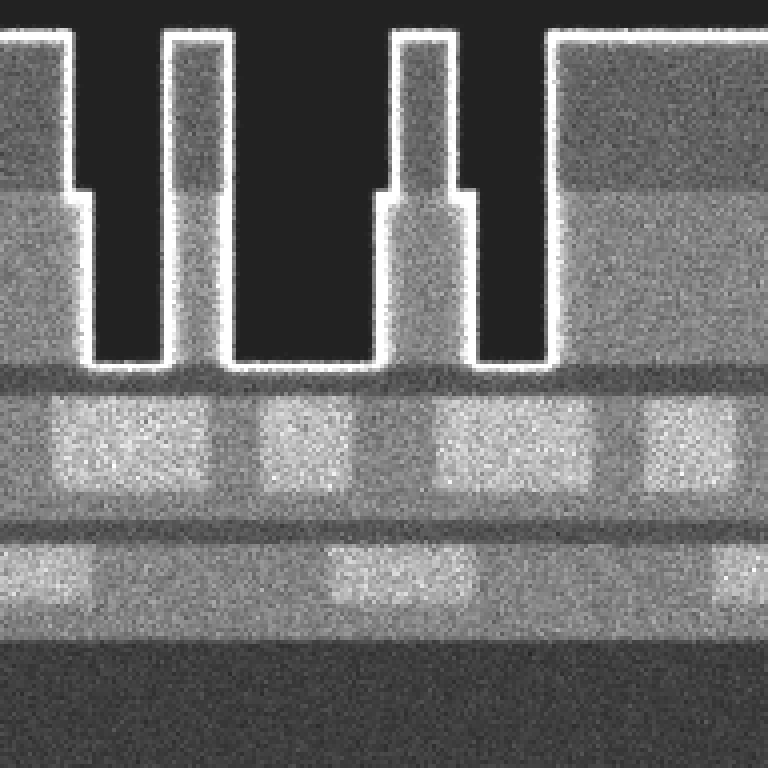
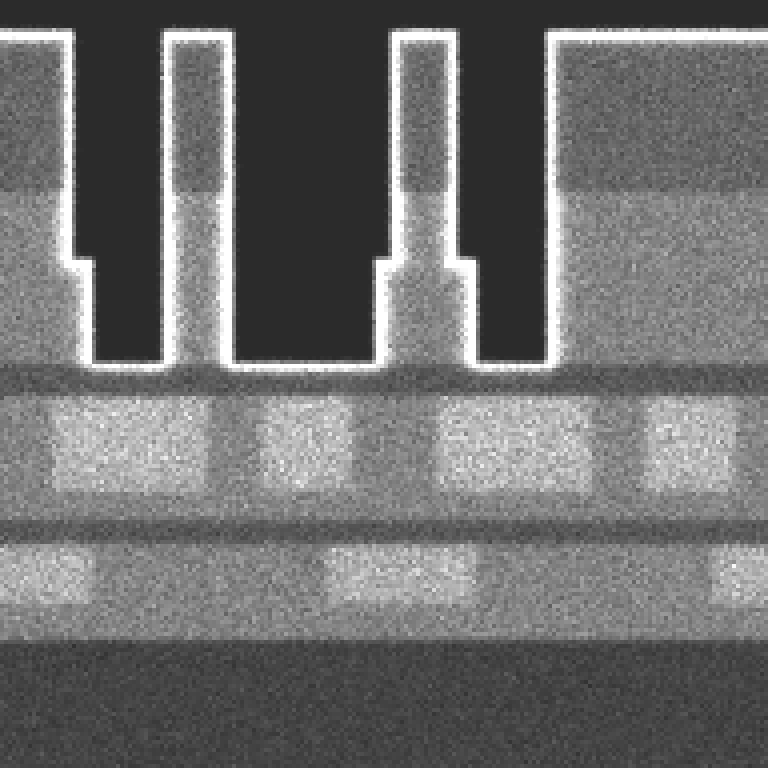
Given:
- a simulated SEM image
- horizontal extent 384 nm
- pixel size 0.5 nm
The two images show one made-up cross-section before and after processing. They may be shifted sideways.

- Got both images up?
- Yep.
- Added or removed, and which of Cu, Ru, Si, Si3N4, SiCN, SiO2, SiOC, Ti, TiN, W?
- removed, SiO2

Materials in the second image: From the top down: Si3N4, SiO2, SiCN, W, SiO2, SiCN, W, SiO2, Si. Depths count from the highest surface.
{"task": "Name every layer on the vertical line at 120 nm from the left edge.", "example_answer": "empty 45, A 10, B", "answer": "empty 166, SiCN 16, SiO2 62, SiCN 12, SiO2 48, Si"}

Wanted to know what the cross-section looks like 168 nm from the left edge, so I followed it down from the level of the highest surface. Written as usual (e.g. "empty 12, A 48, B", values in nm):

empty 166, SiCN 16, W 48, SiO2 14, SiCN 12, W 30, SiO2 18, Si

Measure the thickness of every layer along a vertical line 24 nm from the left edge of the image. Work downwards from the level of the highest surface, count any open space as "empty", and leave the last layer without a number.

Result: Si3N4 80, SiO2 86, SiCN 16, SiO2 62, SiCN 12, W 30, SiO2 18, Si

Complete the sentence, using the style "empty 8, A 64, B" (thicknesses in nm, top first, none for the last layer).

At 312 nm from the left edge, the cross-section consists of Si3N4 80, SiO2 86, SiCN 16, SiO2 62, SiCN 12, SiO2 48, Si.